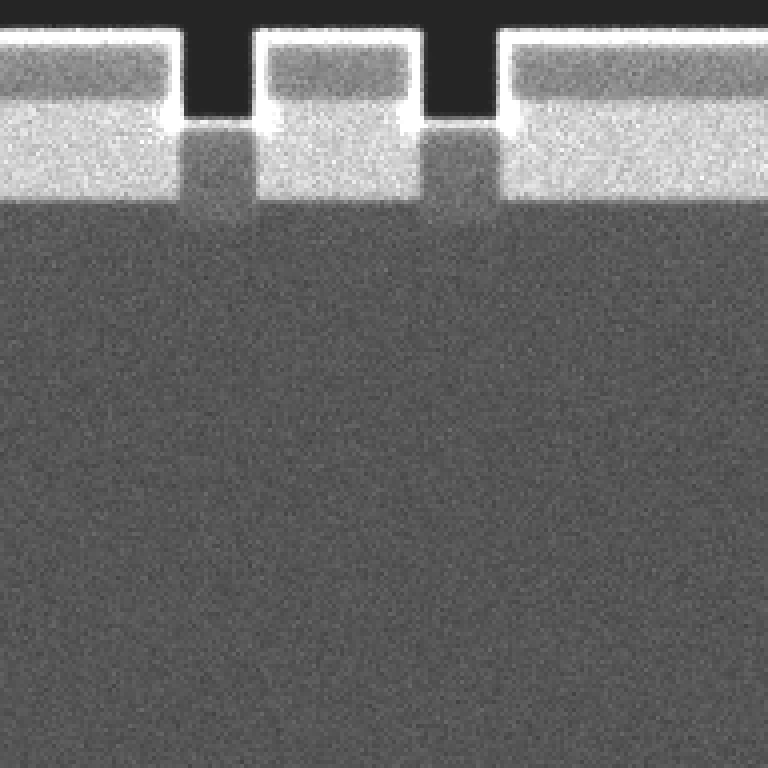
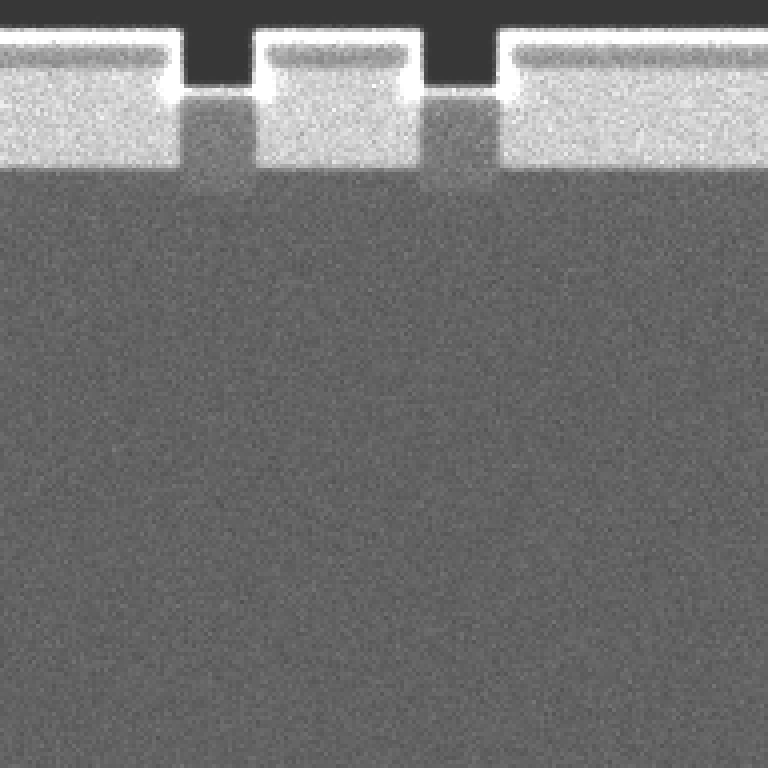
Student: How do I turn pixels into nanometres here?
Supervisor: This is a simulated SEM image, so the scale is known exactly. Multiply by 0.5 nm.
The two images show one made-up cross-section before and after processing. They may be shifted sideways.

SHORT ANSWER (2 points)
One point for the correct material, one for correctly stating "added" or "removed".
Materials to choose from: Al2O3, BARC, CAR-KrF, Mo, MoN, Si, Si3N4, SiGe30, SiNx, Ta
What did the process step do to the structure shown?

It removed SiNx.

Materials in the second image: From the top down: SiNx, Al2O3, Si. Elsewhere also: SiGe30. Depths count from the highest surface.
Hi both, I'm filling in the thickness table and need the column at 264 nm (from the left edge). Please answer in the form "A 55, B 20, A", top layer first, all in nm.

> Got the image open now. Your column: SiNx 18, Al2O3 50, Si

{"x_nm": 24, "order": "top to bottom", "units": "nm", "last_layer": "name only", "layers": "SiNx 18, Al2O3 50, Si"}